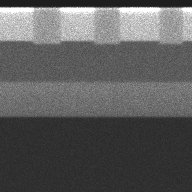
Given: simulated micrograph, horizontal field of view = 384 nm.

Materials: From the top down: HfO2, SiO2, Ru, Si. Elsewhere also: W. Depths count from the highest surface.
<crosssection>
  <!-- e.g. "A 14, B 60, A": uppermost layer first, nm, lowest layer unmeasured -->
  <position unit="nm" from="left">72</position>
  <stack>W 72, SiO2 76, Ru 70, Si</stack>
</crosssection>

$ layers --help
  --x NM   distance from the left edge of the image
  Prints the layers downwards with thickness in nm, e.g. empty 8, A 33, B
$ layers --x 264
HfO2 66, SiO2 82, Ru 70, Si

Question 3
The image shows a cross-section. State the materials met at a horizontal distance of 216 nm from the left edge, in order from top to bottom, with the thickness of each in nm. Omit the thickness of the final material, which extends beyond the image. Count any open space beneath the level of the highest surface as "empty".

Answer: W 72, SiO2 76, Ru 70, Si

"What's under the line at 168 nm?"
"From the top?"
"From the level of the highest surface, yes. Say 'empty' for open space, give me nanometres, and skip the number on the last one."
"HfO2 66, SiO2 82, Ru 70, Si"